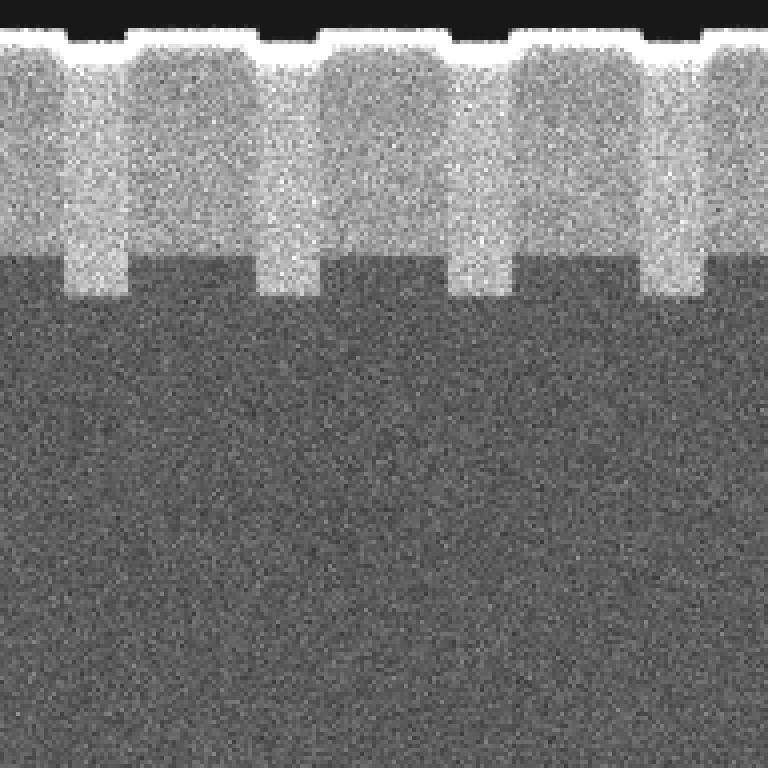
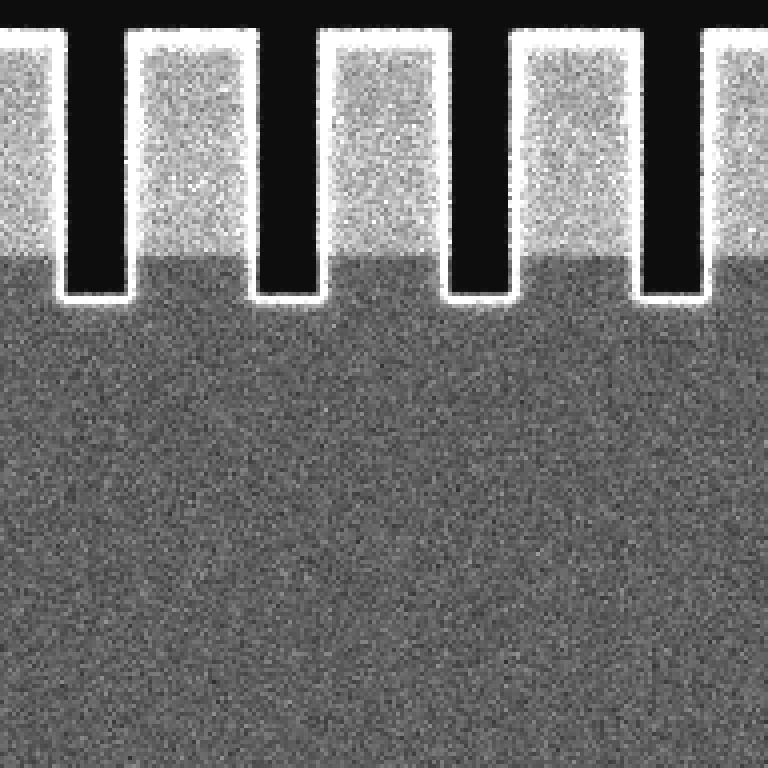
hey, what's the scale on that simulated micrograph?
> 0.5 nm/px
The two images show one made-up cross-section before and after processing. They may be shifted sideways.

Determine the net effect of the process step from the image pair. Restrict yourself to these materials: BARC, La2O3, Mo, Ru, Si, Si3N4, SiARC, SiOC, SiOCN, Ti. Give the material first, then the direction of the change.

SiARC: removed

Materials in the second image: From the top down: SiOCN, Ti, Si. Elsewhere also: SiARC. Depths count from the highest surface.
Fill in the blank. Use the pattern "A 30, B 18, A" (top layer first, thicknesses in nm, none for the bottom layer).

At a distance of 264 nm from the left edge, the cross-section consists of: SiOCN 46, Ti 66, Si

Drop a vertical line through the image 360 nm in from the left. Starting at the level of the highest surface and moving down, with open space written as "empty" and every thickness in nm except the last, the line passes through SiOCN 46, Ti 66, Si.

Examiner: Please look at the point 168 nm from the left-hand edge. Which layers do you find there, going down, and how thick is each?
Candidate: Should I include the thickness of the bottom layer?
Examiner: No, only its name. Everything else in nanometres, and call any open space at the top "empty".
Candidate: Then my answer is SiOCN 46, Ti 66, Si